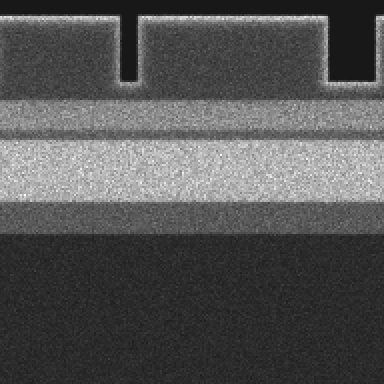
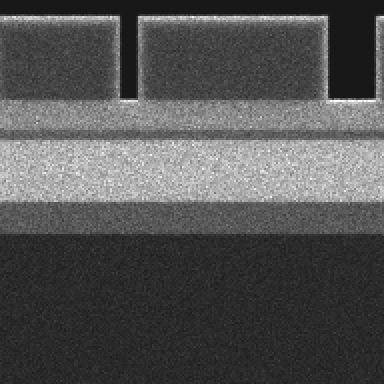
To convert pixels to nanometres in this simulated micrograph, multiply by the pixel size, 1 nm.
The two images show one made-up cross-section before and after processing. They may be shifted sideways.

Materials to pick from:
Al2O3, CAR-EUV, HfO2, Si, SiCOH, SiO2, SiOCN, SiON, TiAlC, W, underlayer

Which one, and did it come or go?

underlayer - removed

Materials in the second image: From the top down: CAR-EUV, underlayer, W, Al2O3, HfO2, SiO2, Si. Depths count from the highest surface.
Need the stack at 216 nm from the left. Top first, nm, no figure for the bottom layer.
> CAR-EUV 66, underlayer 18, W 30, Al2O3 10, HfO2 62, SiO2 32, Si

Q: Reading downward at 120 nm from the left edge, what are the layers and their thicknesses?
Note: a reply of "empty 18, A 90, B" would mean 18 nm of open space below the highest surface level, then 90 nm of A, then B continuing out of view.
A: empty 84, W 30, Al2O3 10, HfO2 62, SiO2 32, Si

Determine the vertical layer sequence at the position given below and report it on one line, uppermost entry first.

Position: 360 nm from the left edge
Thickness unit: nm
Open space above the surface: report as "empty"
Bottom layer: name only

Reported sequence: empty 84, W 30, Al2O3 10, HfO2 62, SiO2 32, Si